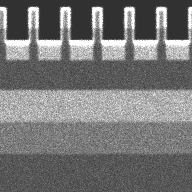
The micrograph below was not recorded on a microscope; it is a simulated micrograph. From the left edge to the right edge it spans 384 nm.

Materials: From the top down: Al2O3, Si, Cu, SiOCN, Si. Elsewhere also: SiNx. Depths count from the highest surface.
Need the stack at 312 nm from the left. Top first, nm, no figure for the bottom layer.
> empty 66, Al2O3 38, Si 60, Cu 64, SiOCN 64, Si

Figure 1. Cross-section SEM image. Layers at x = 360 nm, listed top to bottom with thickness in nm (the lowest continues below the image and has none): empty 66, Al2O3 38, Si 60, Cu 64, SiOCN 64, Si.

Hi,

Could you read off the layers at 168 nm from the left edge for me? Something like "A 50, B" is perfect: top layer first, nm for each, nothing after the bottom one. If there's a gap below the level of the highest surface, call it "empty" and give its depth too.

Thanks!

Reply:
empty 66, Al2O3 38, Si 60, Cu 64, SiOCN 64, Si